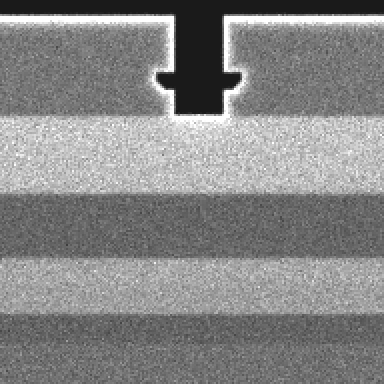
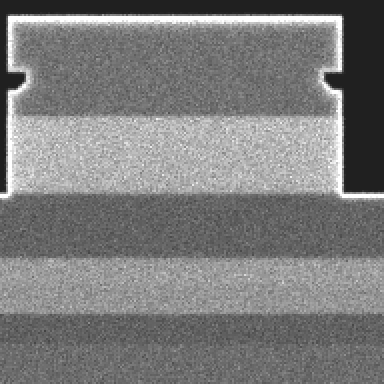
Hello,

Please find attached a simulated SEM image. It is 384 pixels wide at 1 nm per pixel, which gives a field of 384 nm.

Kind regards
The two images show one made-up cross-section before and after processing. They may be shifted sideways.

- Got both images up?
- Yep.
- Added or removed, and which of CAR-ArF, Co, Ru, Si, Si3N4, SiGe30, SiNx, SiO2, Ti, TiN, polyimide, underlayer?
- removed, Ru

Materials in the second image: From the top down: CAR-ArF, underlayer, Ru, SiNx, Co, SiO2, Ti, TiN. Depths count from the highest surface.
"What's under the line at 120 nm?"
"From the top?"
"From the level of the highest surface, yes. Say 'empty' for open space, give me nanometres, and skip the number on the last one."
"CAR-ArF 56, underlayer 44, Ru 78, SiNx 64, Co 26, SiO2 30, Ti 30, TiN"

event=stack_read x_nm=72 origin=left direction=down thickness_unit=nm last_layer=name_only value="CAR-ArF 56, underlayer 44, Ru 78, SiNx 64, Co 26, SiO2 30, Ti 30, TiN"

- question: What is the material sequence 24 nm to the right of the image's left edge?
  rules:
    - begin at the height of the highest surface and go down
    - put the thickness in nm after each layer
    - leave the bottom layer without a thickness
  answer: CAR-ArF 56, empty 10, underlayer 34, Ru 78, SiNx 64, Co 26, SiO2 30, Ti 30, TiN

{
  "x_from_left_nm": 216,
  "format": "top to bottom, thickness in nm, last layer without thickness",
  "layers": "CAR-ArF 56, underlayer 44, Ru 78, SiNx 64, Co 26, SiO2 30, Ti 30, TiN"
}